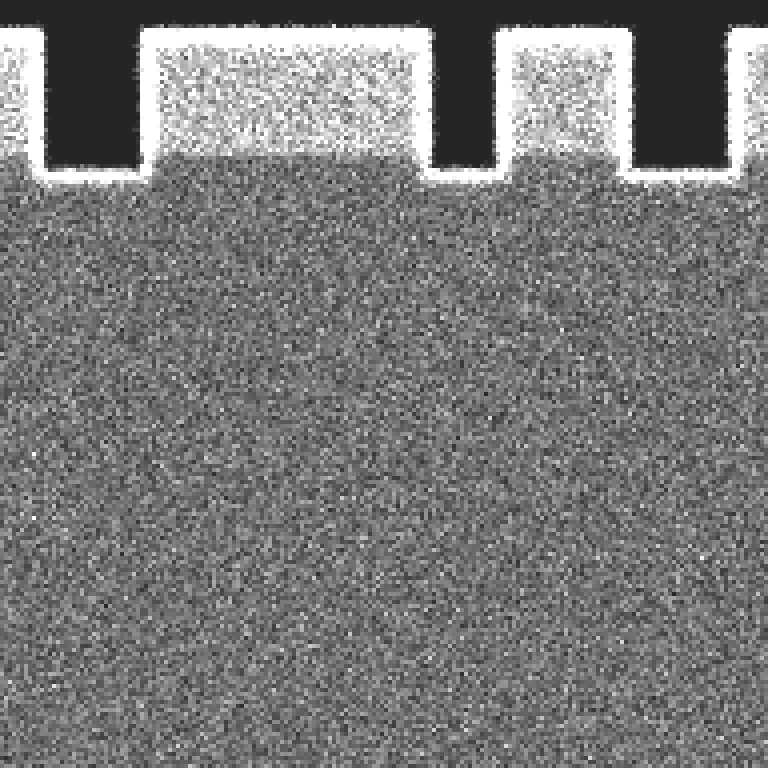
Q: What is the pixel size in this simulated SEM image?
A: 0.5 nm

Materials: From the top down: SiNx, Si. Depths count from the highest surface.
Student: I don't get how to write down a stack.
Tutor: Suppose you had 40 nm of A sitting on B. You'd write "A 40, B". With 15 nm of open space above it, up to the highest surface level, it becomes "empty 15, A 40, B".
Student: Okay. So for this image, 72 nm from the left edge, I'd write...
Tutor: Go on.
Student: SiNx 62, Si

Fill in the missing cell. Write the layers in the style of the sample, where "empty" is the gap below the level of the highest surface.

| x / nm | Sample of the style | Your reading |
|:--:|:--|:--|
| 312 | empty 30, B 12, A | SiNx 62, Si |